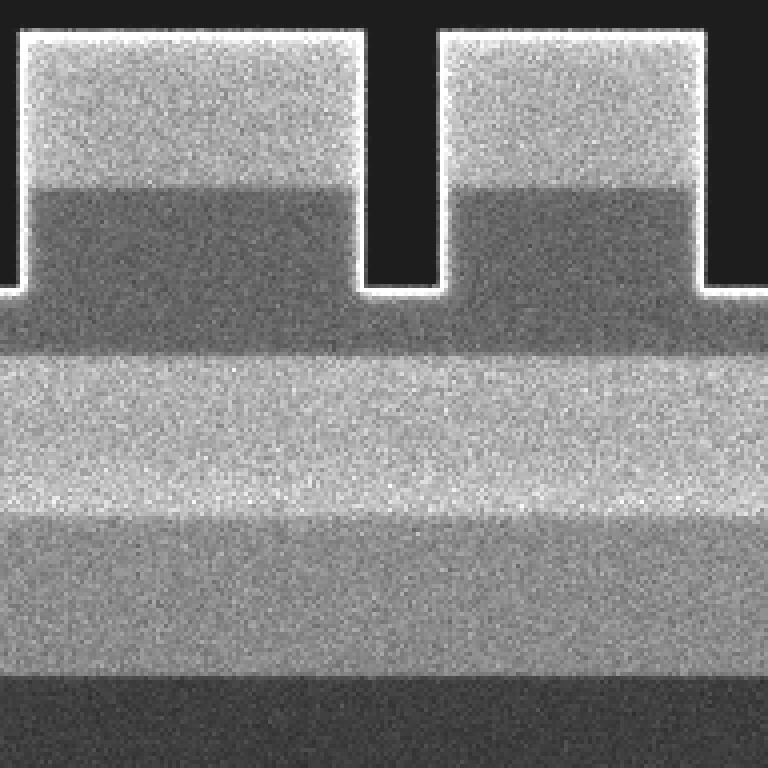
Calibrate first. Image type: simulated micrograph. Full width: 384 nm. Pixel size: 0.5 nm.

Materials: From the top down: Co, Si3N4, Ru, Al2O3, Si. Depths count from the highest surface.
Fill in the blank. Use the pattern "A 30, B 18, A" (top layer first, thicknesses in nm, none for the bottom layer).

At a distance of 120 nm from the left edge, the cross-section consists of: Co 78, Si3N4 84, Ru 80, Al2O3 80, Si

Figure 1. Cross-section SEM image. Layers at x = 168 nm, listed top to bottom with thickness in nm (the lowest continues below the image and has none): Co 78, Si3N4 84, Ru 80, Al2O3 80, Si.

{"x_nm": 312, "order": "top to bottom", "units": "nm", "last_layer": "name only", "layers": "Co 78, Si3N4 84, Ru 80, Al2O3 80, Si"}